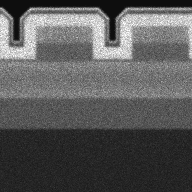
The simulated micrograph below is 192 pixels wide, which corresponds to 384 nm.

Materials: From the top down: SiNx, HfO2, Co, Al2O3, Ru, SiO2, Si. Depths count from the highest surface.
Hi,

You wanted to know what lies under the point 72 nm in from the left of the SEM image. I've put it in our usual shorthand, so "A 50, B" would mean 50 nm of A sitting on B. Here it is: SiNx 12, HfO2 24, Co 34, Al2O3 38, Ru 72, SiO2 62, Si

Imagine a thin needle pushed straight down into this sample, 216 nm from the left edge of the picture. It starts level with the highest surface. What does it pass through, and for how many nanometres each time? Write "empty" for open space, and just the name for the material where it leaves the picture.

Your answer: empty 20, SiNx 58, HfO2 24, Al2O3 6, Ru 72, SiO2 62, Si